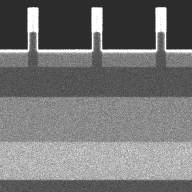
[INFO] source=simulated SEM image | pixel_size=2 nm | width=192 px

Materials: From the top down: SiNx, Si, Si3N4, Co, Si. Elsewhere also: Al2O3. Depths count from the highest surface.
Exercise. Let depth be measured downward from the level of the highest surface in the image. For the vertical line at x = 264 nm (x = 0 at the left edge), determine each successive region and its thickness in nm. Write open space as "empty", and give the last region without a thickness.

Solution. empty 84, SiNx 34, Si 60, Si3N4 90, Co 76, Si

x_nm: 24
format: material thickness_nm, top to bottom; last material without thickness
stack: empty 84, SiNx 34, Si 60, Si3N4 90, Co 76, Si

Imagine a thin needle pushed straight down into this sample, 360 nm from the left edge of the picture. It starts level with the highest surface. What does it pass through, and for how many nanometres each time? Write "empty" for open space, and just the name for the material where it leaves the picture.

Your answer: empty 84, SiNx 34, Si 60, Si3N4 90, Co 76, Si